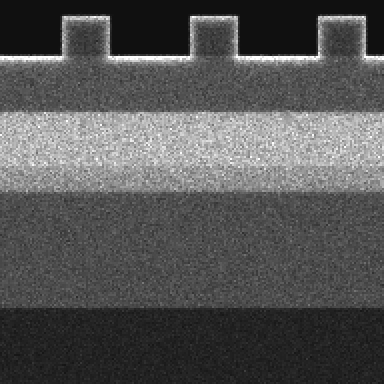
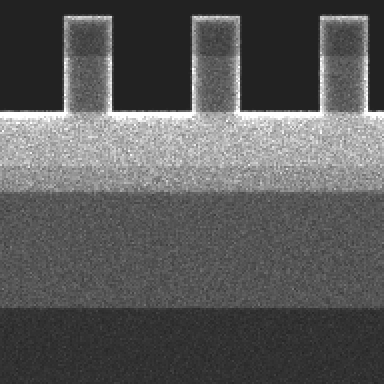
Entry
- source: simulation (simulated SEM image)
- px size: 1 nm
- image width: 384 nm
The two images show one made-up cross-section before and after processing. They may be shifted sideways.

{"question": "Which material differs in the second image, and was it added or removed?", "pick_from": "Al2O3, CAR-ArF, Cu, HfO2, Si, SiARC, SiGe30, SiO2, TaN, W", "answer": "Al2O3, removed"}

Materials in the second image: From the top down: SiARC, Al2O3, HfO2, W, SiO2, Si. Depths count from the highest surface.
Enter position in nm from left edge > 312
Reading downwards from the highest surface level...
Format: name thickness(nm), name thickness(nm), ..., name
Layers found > empty 96, HfO2 54, W 26, SiO2 116, Si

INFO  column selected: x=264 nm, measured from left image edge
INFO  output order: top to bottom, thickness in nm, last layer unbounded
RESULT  empty 96, HfO2 54, W 26, SiO2 116, Si